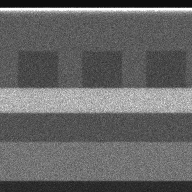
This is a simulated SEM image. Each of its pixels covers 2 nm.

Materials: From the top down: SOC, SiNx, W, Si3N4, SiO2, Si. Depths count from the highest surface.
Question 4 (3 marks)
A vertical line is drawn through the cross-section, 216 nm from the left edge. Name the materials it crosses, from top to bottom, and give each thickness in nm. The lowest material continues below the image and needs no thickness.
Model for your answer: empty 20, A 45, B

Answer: SOC 86, SiNx 74, W 50, Si3N4 58, SiO2 78, Si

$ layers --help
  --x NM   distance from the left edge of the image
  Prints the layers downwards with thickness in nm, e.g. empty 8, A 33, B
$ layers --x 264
SOC 160, W 50, Si3N4 58, SiO2 78, Si